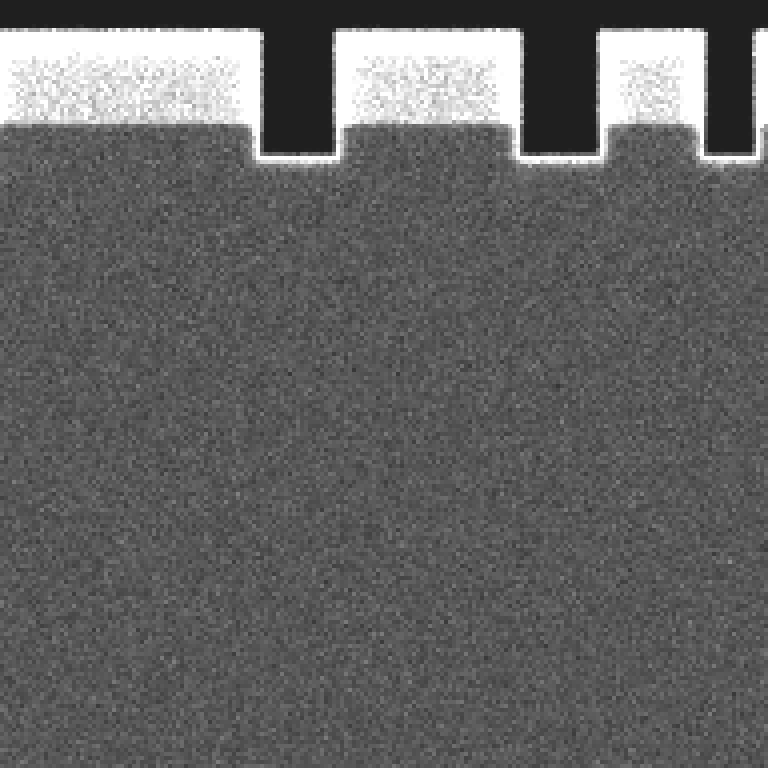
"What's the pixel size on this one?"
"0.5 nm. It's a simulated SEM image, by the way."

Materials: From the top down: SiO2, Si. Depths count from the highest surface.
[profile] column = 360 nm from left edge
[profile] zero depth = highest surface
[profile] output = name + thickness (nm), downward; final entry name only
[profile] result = empty 62, Si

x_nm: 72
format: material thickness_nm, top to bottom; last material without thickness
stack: SiO2 46, Si